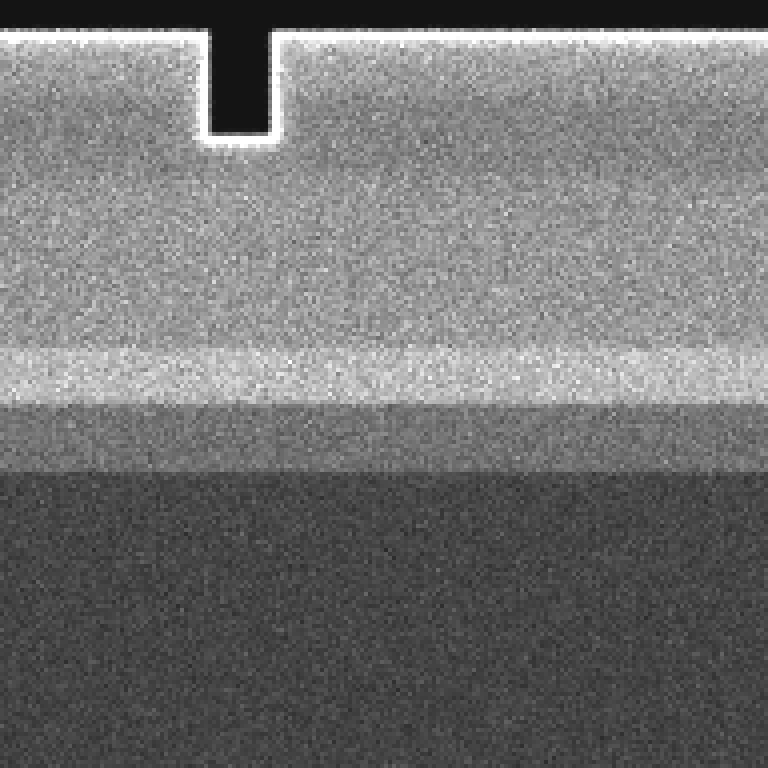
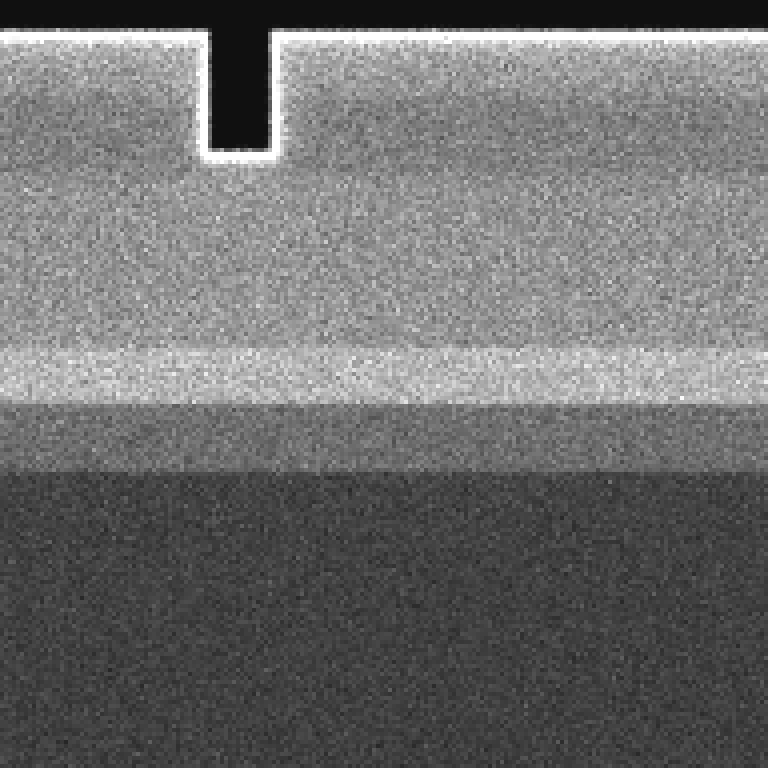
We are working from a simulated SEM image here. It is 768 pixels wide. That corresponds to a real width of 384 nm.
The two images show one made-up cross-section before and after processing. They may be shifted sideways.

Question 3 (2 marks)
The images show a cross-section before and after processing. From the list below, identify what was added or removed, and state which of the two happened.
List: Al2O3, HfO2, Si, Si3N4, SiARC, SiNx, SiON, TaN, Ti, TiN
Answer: Si3N4 was removed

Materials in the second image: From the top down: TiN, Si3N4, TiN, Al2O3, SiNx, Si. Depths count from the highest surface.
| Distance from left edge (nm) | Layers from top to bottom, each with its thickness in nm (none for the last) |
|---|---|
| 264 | TiN 32, Si3N4 40, TiN 86, Al2O3 28, SiNx 34, Si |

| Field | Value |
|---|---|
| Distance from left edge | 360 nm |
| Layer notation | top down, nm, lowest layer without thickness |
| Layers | TiN 32, Si3N4 40, TiN 86, Al2O3 28, SiNx 34, Si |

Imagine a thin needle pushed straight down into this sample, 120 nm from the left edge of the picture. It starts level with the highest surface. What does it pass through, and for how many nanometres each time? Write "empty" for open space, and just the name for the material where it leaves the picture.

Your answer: empty 60, Si3N4 12, TiN 86, Al2O3 28, SiNx 34, Si